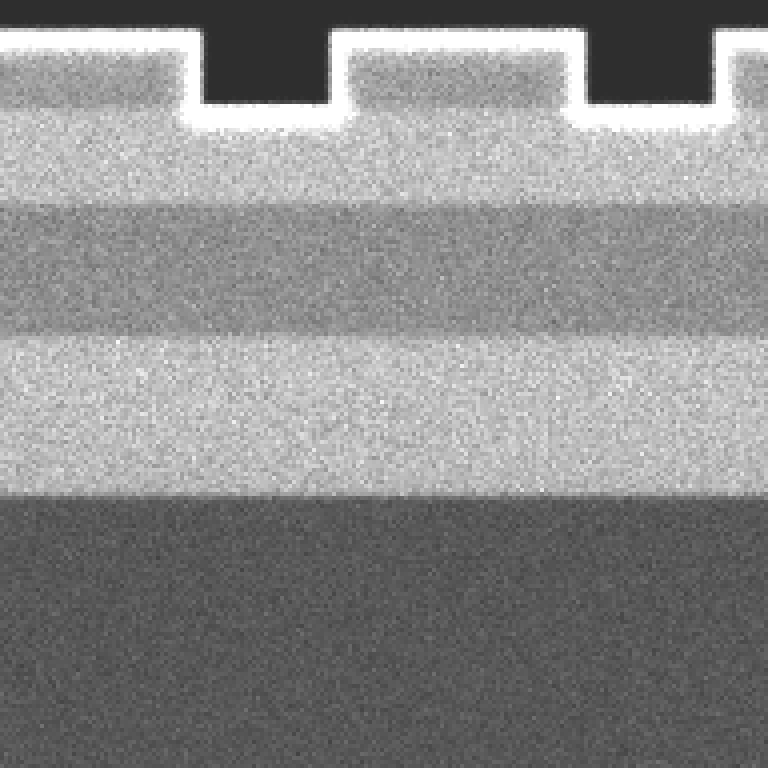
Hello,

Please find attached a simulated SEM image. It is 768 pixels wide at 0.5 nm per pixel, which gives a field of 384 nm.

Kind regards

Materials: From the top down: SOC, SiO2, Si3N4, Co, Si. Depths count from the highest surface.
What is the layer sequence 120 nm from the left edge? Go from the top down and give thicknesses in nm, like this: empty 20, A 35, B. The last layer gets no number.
empty 38, SiO2 48, Si3N4 66, Co 80, Si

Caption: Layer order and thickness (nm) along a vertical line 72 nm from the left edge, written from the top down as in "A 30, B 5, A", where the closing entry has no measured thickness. SOC 38, SiO2 48, Si3N4 66, Co 80, Si